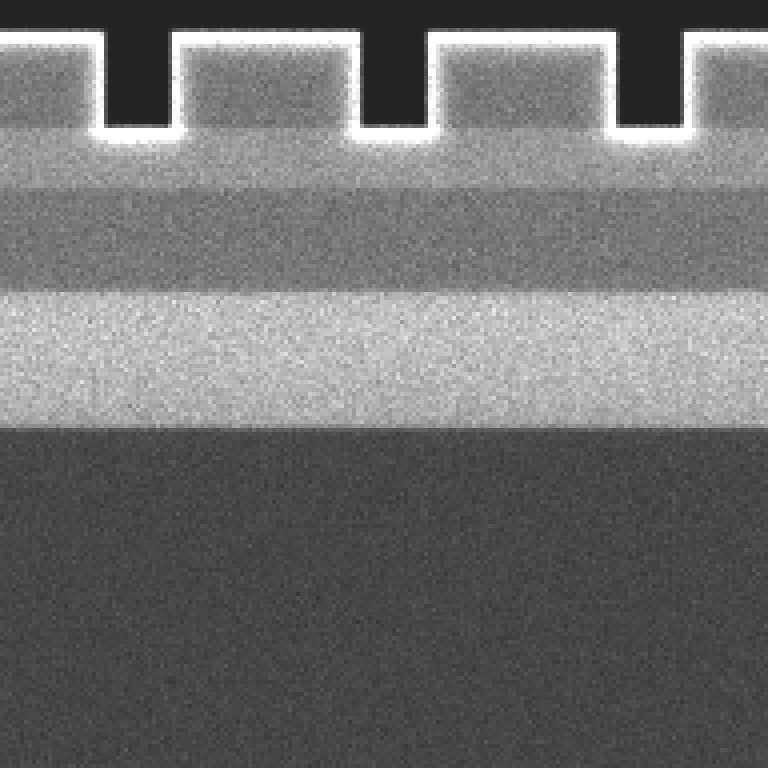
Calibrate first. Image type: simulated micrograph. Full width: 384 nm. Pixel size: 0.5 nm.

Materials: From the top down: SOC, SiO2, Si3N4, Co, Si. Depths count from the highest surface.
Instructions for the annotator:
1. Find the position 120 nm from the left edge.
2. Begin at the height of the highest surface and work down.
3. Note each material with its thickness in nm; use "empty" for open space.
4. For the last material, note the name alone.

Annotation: SOC 48, SiO2 30, Si3N4 52, Co 68, Si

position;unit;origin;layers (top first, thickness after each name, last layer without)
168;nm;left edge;SOC 48, SiO2 30, Si3N4 52, Co 68, Si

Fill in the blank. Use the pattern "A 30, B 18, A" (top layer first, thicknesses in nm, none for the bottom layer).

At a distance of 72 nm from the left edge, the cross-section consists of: empty 48, SiO2 30, Si3N4 52, Co 68, Si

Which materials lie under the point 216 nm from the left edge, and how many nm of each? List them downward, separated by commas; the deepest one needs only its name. SOC 48, SiO2 30, Si3N4 52, Co 68, Si